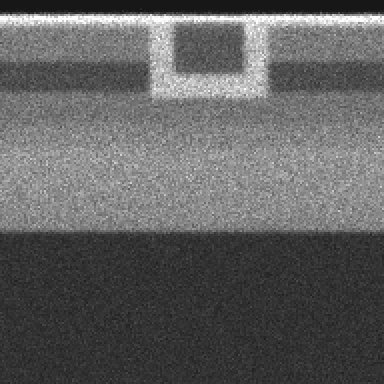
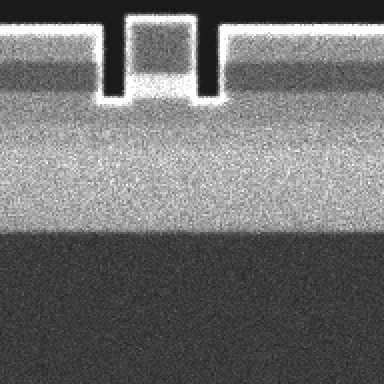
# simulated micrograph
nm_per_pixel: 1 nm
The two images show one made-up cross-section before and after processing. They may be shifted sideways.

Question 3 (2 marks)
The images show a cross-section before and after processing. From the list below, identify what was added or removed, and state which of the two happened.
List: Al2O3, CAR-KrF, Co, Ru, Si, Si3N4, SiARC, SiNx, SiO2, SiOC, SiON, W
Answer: W was removed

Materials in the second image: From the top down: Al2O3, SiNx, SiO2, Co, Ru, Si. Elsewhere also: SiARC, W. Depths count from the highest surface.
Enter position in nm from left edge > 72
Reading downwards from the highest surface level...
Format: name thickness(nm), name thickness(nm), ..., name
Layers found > empty 10, Al2O3 36, SiNx 30, SiO2 32, Co 24, Ru 84, Si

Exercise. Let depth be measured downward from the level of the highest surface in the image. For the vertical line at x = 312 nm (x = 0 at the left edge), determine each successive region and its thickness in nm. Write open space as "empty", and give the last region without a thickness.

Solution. empty 10, Al2O3 36, SiNx 30, SiO2 32, Co 24, Ru 84, Si